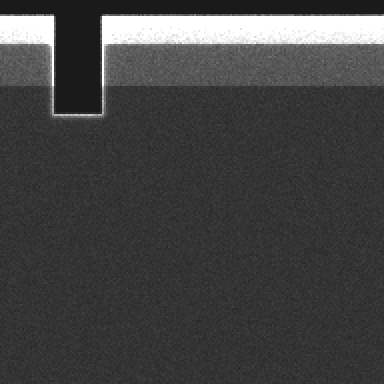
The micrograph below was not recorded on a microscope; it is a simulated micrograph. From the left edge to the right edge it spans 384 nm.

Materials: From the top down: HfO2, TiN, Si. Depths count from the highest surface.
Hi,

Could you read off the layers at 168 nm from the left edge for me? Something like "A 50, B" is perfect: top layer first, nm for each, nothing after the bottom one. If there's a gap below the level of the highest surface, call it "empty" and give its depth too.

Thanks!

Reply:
HfO2 28, TiN 42, Si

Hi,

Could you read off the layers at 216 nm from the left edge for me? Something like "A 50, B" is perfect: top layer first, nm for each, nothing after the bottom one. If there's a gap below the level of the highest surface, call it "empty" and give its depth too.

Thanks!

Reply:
HfO2 28, TiN 42, Si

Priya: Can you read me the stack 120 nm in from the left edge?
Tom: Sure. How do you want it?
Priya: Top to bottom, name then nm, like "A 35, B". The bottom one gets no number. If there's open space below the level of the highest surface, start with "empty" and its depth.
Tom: HfO2 28, TiN 42, Si